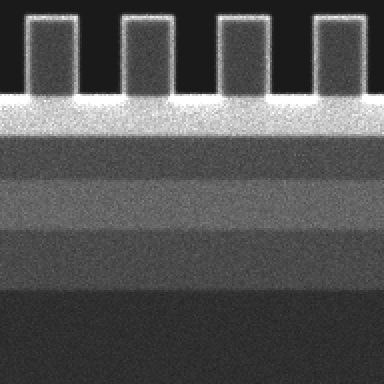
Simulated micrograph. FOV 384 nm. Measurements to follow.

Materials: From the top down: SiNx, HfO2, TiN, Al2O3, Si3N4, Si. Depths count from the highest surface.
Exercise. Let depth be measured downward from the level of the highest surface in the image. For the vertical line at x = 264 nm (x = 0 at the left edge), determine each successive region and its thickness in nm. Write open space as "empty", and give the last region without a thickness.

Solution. SiNx 80, HfO2 40, TiN 44, Al2O3 50, Si3N4 60, Si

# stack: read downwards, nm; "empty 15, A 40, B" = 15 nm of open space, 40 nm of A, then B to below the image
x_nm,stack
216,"empty 80, HfO2 40, TiN 44, Al2O3 50, Si3N4 60, Si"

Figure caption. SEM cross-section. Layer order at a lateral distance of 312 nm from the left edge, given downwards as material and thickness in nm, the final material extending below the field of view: empty 80, HfO2 40, TiN 44, Al2O3 50, Si3N4 60, Si